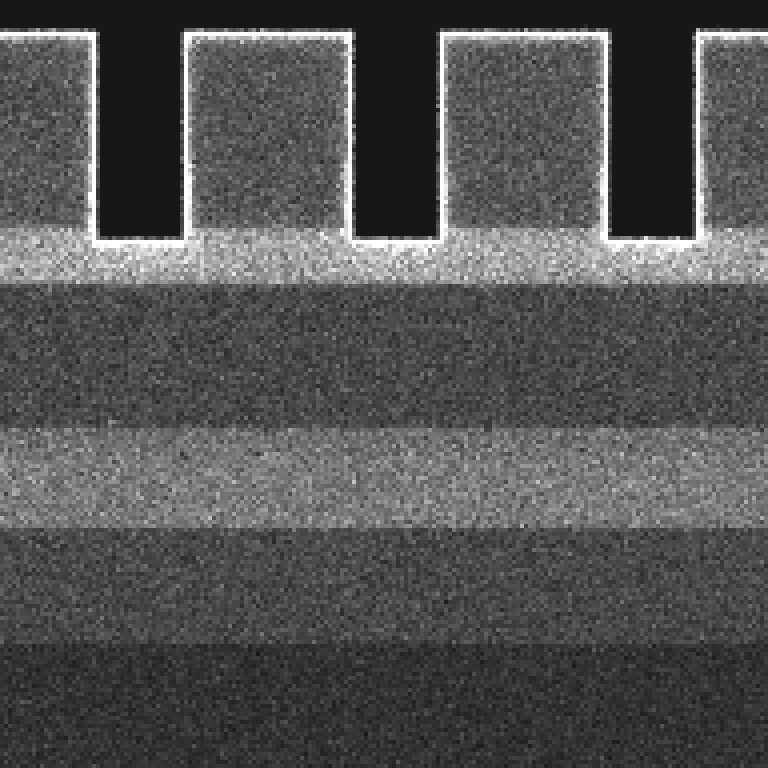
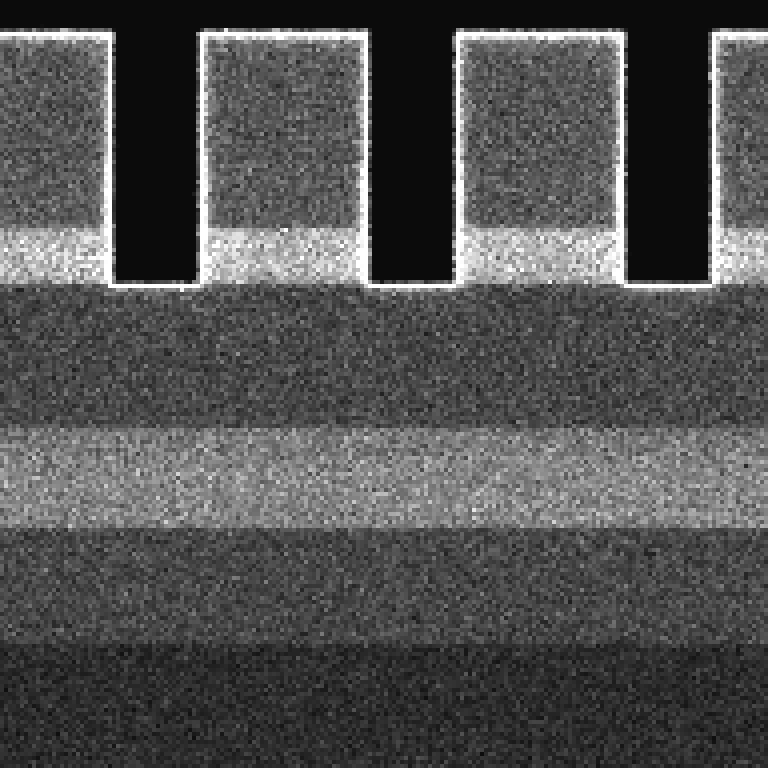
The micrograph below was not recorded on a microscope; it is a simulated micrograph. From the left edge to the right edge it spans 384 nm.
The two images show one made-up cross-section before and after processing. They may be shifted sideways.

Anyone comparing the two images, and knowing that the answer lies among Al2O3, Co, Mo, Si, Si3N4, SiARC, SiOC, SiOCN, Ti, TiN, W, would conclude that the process removed W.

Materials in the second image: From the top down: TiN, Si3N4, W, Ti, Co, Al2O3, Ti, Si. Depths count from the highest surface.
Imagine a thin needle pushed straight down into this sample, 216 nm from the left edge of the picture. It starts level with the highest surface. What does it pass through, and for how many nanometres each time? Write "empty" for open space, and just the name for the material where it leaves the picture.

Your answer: empty 126, Ti 72, Co 14, Al2O3 36, Ti 58, Si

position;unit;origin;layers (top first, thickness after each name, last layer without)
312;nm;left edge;empty 126, Ti 72, Co 14, Al2O3 36, Ti 58, Si